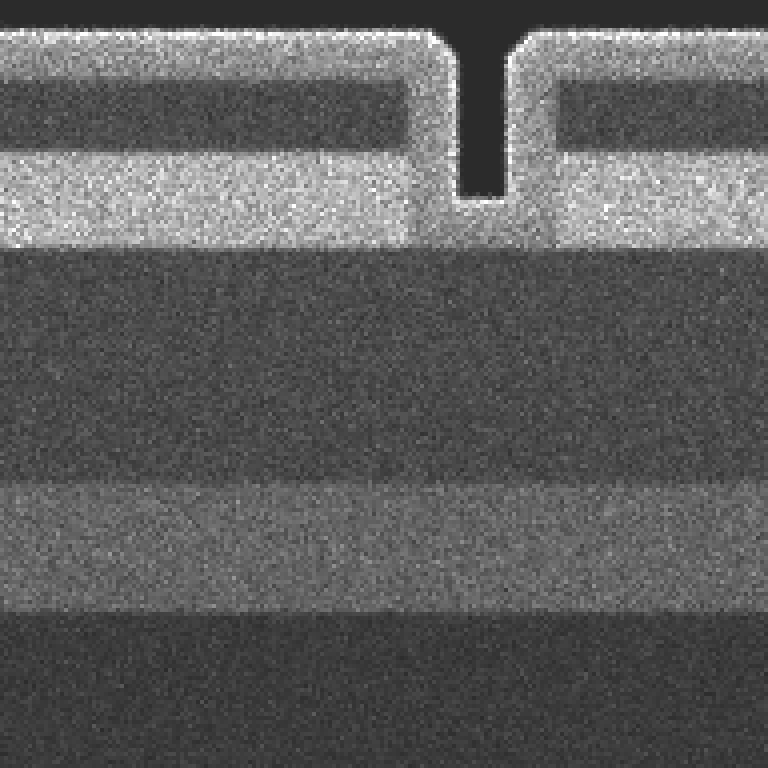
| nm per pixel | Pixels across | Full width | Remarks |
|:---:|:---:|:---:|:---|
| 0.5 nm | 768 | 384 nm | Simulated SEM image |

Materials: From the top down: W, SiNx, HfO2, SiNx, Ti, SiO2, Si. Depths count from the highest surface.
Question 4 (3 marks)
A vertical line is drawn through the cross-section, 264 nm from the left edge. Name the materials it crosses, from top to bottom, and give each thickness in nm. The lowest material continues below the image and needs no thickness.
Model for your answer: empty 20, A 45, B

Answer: empty 2, W 106, SiNx 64, Ti 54, SiO2 64, Si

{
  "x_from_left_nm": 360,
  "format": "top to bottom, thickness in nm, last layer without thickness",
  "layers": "W 24, SiNx 36, HfO2 48, SiNx 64, Ti 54, SiO2 64, Si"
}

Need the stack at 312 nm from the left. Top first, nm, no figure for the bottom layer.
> W 24, SiNx 36, HfO2 48, SiNx 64, Ti 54, SiO2 64, Si